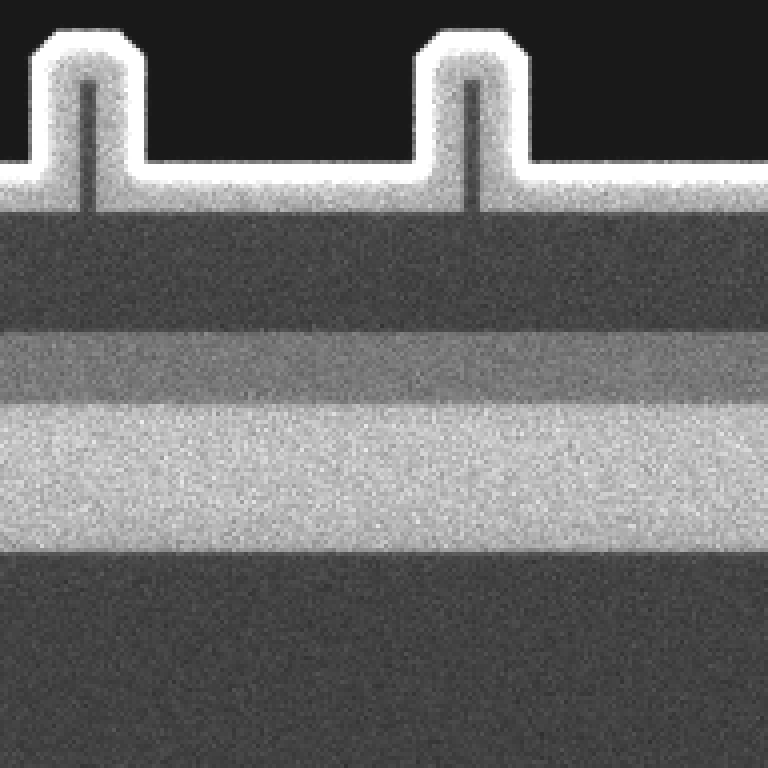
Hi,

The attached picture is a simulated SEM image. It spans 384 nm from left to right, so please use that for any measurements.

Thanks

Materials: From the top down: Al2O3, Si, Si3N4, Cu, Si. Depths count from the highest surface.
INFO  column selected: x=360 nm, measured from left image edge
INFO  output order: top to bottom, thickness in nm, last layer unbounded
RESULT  empty 66, Al2O3 24, Si 60, Si3N4 36, Cu 74, Si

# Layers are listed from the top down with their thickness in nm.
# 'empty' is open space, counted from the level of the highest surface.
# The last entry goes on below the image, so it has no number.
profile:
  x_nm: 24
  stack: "empty 4, Al2O3 86, Si 60, Si3N4 36, Cu 74, Si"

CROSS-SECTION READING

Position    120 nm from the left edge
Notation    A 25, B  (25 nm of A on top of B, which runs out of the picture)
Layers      empty 66, Al2O3 24, Si 60, Si3N4 36, Cu 74, Si